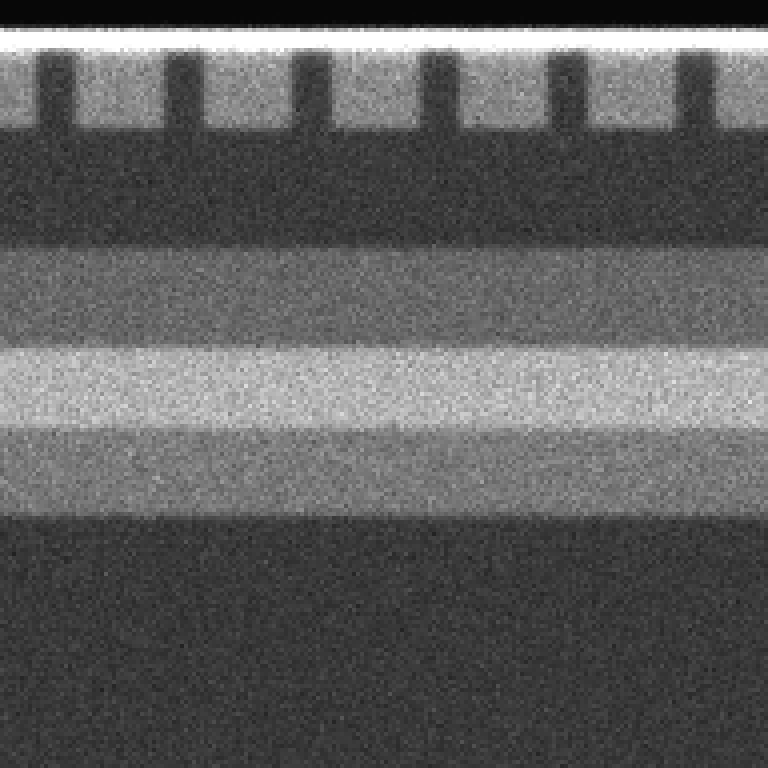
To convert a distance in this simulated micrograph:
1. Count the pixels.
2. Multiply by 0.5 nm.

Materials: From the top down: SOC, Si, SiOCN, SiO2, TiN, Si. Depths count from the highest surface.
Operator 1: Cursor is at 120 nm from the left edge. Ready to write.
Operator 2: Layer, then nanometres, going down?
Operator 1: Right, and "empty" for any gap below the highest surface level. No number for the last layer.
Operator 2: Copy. SOC 48, Si 60, SiOCN 50, SiO2 40, TiN 44, Si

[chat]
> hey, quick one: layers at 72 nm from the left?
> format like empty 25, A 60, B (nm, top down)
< SOC 48, Si 60, SiOCN 50, SiO2 40, TiN 44, Si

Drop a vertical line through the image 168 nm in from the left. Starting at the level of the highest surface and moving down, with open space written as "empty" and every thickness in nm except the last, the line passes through SOC 48, Si 60, SiOCN 50, SiO2 40, TiN 44, Si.